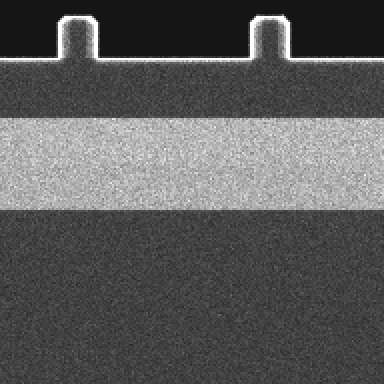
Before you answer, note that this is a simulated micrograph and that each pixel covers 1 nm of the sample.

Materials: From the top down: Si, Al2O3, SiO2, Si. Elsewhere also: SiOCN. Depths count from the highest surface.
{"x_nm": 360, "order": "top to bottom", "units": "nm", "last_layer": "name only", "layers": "empty 42, Si 60, Al2O3 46, SiO2 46, Si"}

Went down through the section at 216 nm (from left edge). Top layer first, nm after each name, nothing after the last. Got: empty 42, Si 60, Al2O3 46, SiO2 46, Si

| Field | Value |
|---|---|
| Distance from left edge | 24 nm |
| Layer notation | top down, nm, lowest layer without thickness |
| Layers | empty 42, Si 60, Al2O3 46, SiO2 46, Si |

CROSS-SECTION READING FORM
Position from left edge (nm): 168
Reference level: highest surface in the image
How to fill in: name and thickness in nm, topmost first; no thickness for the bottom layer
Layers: empty 42, Si 60, Al2O3 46, SiO2 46, Si